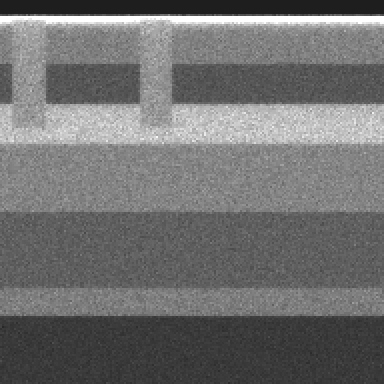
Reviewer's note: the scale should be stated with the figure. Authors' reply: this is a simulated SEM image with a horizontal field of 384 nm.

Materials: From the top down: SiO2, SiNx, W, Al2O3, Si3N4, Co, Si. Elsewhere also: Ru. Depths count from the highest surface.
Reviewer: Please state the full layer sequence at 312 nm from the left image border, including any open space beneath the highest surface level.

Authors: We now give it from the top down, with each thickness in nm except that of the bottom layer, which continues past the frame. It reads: SiO2 48, SiNx 40, W 40, Al2O3 68, Si3N4 76, Co 28, Si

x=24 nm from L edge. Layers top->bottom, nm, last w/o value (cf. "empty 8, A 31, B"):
Ru 112, W 16, Al2O3 68, Si3N4 76, Co 28, Si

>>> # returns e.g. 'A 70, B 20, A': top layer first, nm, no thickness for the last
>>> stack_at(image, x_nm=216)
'SiO2 48, SiNx 40, W 40, Al2O3 68, Si3N4 76, Co 28, Si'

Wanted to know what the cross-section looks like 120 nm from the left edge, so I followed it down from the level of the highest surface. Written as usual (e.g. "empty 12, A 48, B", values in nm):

SiO2 48, SiNx 40, W 40, Al2O3 68, Si3N4 76, Co 28, Si